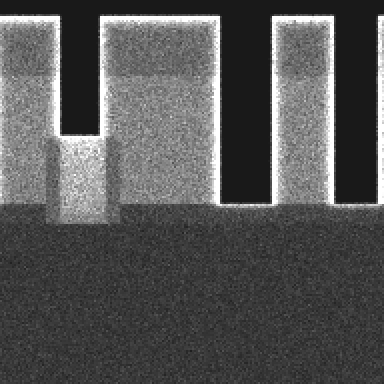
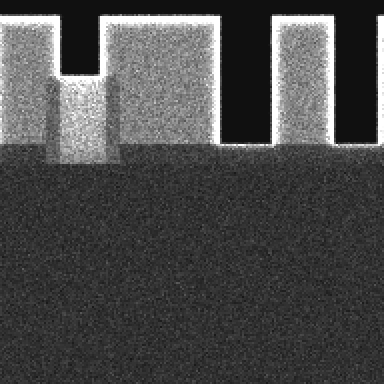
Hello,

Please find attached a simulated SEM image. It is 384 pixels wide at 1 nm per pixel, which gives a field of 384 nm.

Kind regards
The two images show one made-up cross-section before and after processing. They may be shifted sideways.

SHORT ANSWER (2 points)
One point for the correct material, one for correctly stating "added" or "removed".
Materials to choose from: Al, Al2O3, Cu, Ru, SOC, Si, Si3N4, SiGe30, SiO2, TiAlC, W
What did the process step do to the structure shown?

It removed SOC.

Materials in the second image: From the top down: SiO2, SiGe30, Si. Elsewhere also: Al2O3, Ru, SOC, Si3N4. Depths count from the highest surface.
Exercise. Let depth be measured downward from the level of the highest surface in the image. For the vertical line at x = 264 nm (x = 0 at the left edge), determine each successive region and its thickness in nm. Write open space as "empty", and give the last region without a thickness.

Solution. empty 128, SiGe30 20, Si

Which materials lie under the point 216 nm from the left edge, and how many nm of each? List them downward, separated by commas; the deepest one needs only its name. SiO2 128, SiGe30 20, Si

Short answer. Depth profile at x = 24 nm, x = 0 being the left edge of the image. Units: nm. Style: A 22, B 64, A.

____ SiO2 128, SiGe30 20, Si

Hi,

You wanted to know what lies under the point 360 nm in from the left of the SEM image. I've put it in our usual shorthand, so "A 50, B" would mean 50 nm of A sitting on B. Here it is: empty 128, SiGe30 20, Si